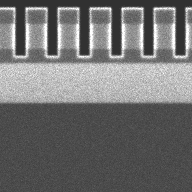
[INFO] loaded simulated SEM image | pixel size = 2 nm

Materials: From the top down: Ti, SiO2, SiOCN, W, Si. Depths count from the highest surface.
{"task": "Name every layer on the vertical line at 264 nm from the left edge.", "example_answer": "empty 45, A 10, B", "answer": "Ti 32, SiO2 50, SiOCN 28, W 80, Si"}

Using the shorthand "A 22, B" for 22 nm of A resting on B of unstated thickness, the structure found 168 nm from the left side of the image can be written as empty 96, SiOCN 14, W 80, Si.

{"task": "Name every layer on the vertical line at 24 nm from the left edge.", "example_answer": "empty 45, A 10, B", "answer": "Ti 32, SiO2 50, SiOCN 28, W 80, Si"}